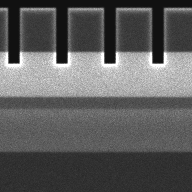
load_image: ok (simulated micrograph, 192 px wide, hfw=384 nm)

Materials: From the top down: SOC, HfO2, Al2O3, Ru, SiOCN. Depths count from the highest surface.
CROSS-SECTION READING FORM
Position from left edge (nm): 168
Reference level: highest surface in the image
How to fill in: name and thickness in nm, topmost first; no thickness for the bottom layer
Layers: SOC 88, HfO2 90, Al2O3 24, Ru 86, SiOCN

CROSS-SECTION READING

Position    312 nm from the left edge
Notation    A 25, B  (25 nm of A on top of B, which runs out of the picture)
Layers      empty 112, HfO2 66, Al2O3 24, Ru 86, SiOCN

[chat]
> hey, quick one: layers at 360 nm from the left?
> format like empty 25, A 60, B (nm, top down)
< SOC 88, HfO2 90, Al2O3 24, Ru 86, SiOCN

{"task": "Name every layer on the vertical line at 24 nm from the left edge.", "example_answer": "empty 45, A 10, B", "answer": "empty 112, HfO2 66, Al2O3 24, Ru 86, SiOCN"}